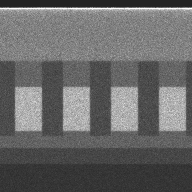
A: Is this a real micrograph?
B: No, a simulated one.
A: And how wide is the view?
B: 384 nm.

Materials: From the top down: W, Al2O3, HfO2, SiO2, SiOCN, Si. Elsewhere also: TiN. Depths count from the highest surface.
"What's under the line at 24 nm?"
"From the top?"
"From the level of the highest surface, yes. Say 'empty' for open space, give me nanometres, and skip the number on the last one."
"W 106, TiN 150, SiO2 24, SiOCN 32, Si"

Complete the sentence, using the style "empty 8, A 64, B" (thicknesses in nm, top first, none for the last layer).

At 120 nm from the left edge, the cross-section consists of W 106, TiN 150, SiO2 24, SiOCN 32, Si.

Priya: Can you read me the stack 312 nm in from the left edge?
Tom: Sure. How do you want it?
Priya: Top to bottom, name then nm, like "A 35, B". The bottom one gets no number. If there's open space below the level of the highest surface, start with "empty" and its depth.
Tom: W 106, TiN 150, SiO2 24, SiOCN 32, Si